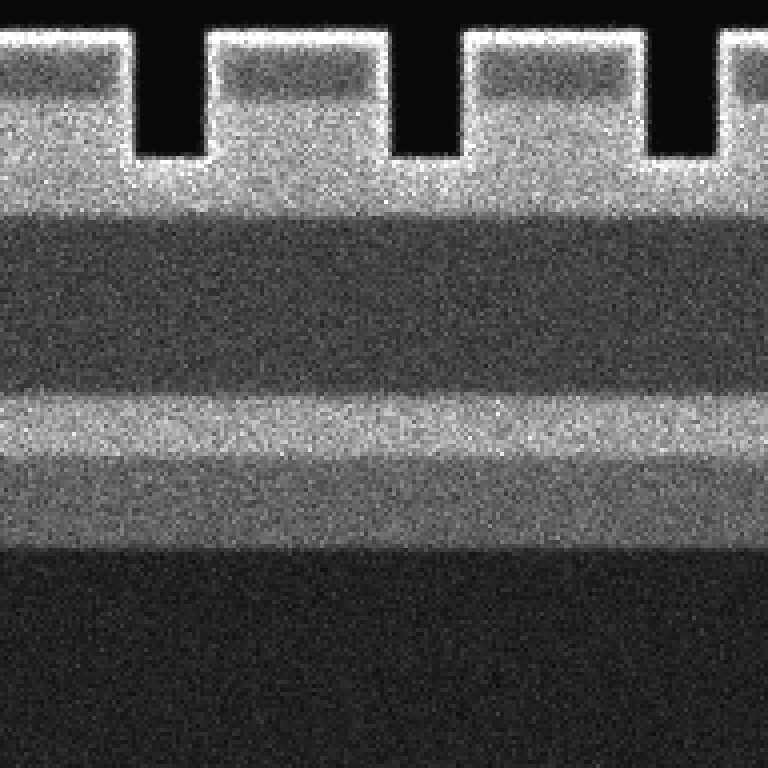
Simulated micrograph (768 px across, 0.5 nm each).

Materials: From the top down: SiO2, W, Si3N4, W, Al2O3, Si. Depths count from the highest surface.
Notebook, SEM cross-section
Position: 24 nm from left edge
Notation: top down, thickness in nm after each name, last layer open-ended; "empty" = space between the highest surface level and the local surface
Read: SiO2 34, W 58, Si3N4 90, W 30, Al2O3 46, Si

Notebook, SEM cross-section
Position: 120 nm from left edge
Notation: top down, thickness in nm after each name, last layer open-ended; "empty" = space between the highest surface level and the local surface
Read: SiO2 34, W 58, Si3N4 90, W 30, Al2O3 46, Si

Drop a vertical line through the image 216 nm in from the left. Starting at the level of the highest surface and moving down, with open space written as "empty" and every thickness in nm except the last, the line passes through empty 64, W 28, Si3N4 90, W 30, Al2O3 46, Si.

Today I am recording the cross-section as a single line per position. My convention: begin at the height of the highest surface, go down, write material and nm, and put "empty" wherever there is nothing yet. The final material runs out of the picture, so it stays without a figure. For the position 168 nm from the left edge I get SiO2 34, W 58, Si3N4 90, W 30, Al2O3 46, Si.